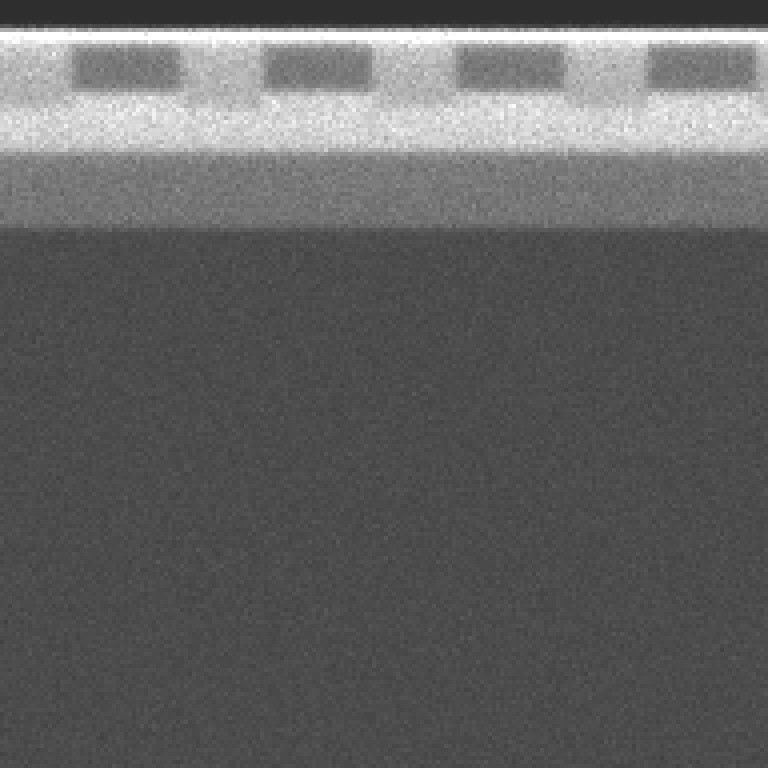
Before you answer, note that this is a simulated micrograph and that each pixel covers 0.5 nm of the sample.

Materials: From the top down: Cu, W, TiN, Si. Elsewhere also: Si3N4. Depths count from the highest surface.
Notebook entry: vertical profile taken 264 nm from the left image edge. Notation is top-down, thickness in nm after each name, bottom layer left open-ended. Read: Si3N4 30, W 30, TiN 38, Si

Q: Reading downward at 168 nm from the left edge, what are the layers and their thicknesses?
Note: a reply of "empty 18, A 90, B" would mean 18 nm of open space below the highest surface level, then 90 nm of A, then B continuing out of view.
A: Si3N4 30, W 30, TiN 38, Si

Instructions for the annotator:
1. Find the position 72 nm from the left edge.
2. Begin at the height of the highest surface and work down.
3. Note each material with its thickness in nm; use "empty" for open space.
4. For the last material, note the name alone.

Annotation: Si3N4 30, W 30, TiN 38, Si